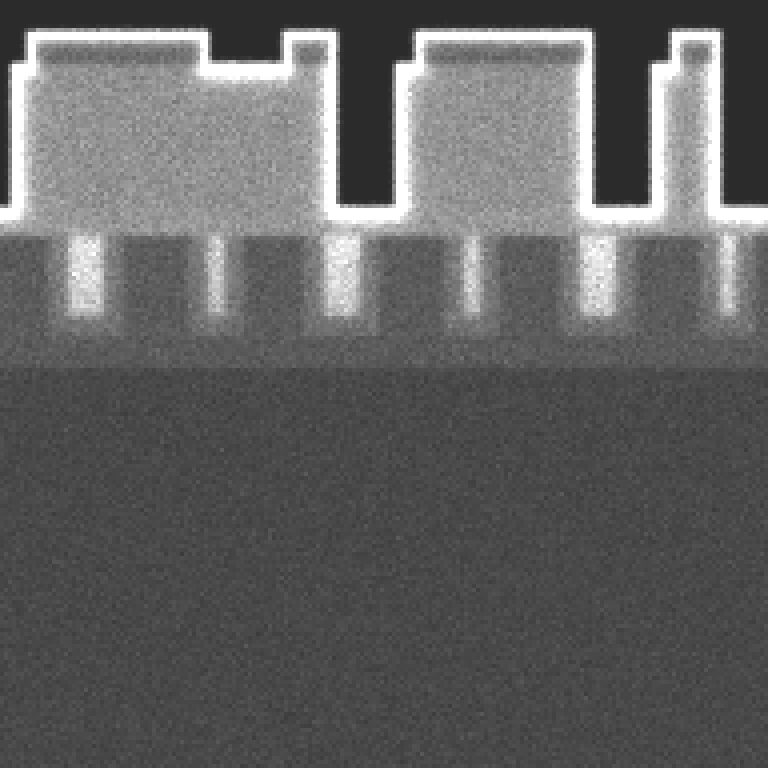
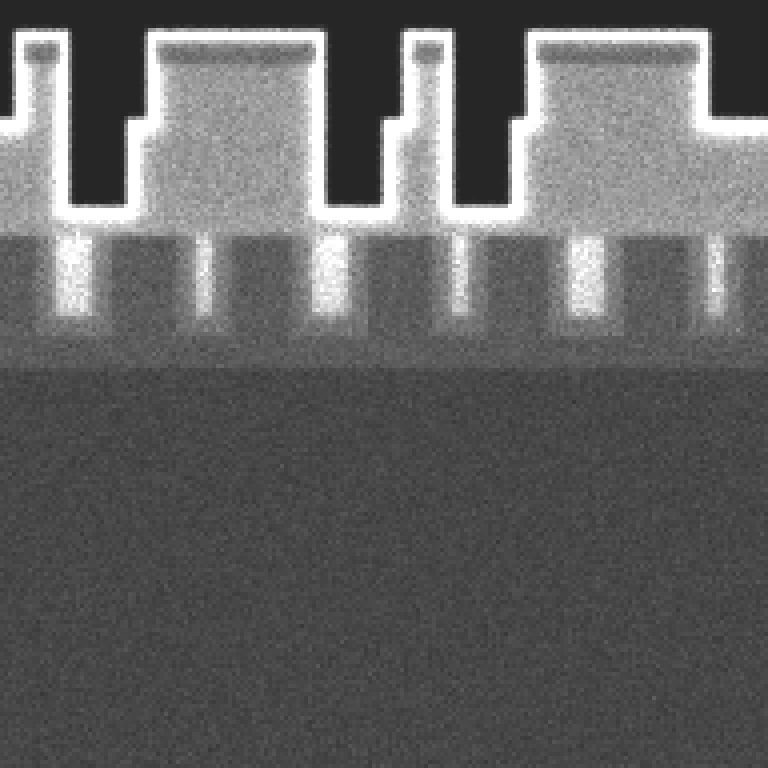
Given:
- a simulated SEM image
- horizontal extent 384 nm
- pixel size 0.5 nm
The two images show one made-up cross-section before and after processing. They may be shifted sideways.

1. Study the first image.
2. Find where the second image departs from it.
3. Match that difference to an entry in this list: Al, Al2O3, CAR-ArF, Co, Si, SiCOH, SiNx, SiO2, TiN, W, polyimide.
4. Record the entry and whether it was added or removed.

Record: SiO2 / removed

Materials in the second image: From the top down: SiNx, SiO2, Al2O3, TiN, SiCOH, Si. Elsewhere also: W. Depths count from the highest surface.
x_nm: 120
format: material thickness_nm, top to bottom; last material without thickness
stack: SiNx 16, SiO2 72, Al2O3 14, SiCOH 66, Si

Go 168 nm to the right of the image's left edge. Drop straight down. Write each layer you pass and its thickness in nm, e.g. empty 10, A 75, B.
empty 88, Al2O3 14, W 40, TiN 10, SiCOH 16, Si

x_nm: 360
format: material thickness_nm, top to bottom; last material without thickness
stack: empty 44, SiO2 44, Al2O3 14, W 40, TiN 10, SiCOH 16, Si